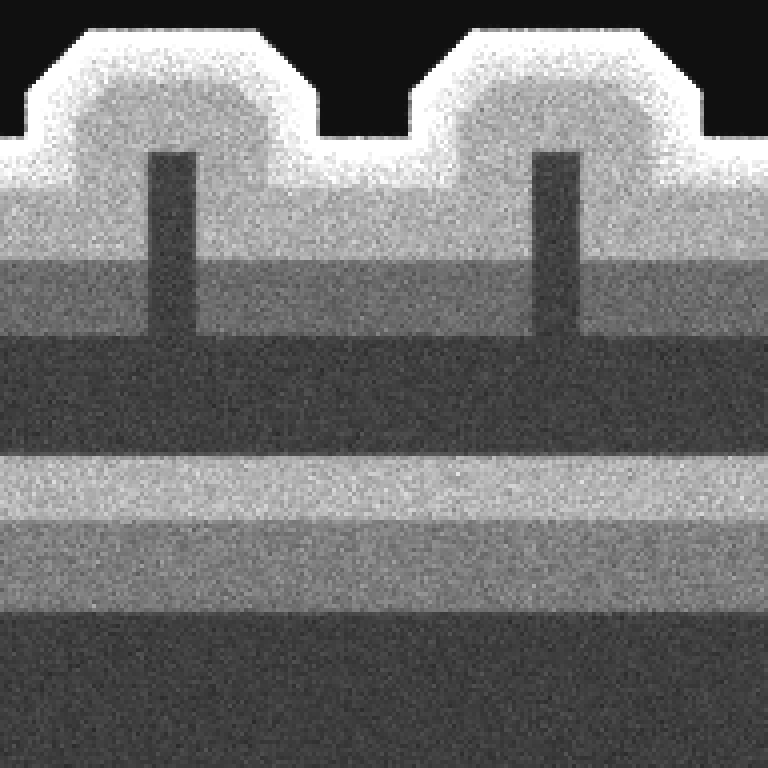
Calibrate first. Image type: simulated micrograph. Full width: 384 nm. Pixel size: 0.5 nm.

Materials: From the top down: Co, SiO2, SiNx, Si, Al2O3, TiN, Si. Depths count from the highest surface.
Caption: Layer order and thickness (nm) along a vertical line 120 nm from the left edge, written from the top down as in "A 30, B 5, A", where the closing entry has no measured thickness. Co 30, SiO2 84, SiNx 38, Si 60, Al2O3 32, TiN 46, Si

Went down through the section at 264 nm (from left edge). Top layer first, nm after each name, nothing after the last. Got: Co 24, SiO2 90, SiNx 38, Si 60, Al2O3 32, TiN 46, Si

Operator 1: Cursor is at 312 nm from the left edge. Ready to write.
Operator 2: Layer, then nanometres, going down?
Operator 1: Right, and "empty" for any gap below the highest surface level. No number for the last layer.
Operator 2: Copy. Co 30, SiO2 84, SiNx 38, Si 60, Al2O3 32, TiN 46, Si